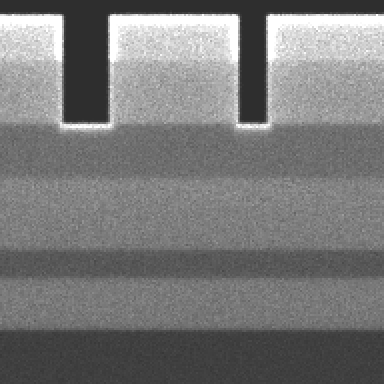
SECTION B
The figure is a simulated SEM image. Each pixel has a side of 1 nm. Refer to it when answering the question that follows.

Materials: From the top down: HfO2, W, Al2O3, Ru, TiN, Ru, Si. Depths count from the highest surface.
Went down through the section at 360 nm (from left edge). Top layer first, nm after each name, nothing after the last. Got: HfO2 44, W 64, Al2O3 54, Ru 72, TiN 28, Ru 52, Si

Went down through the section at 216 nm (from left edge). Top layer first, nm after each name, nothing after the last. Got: HfO2 44, W 64, Al2O3 54, Ru 72, TiN 28, Ru 52, Si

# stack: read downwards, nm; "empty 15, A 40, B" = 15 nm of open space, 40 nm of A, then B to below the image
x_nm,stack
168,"HfO2 44, W 64, Al2O3 54, Ru 72, TiN 28, Ru 52, Si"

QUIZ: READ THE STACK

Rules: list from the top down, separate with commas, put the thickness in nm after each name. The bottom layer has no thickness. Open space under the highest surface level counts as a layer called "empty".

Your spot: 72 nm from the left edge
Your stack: empty 108, Al2O3 54, Ru 72, TiN 28, Ru 52, Si